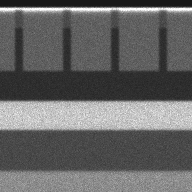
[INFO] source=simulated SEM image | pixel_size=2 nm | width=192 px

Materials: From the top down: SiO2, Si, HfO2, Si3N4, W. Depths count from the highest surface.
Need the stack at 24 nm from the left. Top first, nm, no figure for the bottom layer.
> SiO2 126, Si 60, HfO2 58, Si3N4 82, W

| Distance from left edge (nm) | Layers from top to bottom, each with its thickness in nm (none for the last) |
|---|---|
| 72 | SiO2 126, Si 60, HfO2 58, Si3N4 82, W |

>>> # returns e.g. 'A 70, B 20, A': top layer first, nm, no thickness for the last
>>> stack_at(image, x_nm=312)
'SiO2 126, Si 60, HfO2 58, Si3N4 82, W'